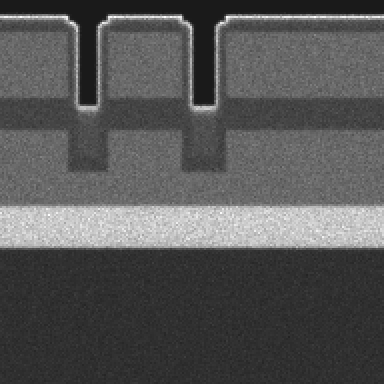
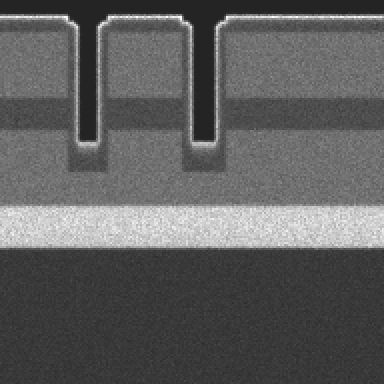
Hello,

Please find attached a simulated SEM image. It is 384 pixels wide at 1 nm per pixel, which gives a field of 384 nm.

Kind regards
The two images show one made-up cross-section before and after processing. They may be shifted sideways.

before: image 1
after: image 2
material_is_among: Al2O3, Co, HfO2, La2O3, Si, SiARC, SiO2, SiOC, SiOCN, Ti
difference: SiARC, removed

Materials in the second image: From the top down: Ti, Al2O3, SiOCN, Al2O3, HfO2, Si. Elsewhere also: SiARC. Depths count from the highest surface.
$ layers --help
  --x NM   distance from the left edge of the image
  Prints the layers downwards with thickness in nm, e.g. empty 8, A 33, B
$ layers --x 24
Ti 16, Al2O3 66, SiOCN 32, Al2O3 76, HfO2 42, Si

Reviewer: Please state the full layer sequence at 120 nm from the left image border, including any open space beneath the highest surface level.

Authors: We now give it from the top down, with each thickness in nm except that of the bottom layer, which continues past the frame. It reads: Ti 16, Al2O3 66, SiOCN 32, Al2O3 76, HfO2 42, Si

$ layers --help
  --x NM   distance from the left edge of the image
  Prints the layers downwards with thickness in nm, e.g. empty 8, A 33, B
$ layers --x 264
Ti 16, Al2O3 66, SiOCN 32, Al2O3 76, HfO2 42, Si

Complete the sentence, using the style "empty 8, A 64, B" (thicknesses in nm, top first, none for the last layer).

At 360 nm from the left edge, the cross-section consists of Ti 16, Al2O3 66, SiOCN 32, Al2O3 76, HfO2 42, Si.